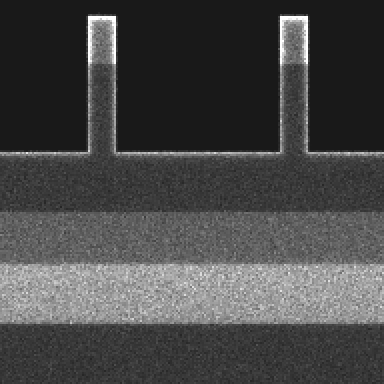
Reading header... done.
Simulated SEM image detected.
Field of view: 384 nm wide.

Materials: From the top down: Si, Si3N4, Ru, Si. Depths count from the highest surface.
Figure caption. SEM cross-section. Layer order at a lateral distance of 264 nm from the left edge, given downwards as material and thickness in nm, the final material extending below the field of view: empty 136, Si 60, Si3N4 52, Ru 60, Si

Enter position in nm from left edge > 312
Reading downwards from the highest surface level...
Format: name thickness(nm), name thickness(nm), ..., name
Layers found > empty 136, Si 60, Si3N4 52, Ru 60, Si